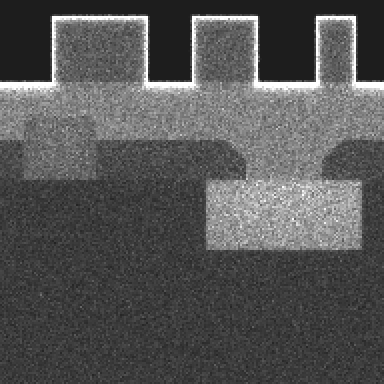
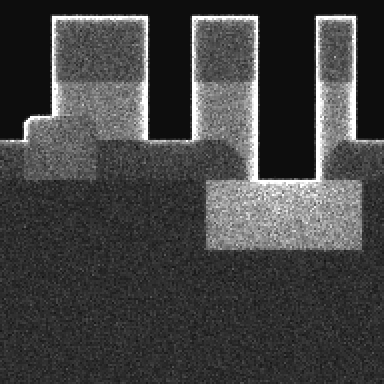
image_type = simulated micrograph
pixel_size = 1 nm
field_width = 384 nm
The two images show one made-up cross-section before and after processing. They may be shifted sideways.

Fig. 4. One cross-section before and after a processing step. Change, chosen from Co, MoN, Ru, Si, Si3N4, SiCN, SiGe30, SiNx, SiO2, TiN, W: SiO2 removed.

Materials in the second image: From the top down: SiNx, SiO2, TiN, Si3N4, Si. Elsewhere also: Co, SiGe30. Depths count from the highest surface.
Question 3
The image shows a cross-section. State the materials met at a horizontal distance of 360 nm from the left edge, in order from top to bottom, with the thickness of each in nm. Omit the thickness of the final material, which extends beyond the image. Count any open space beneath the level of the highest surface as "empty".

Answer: empty 124, SiGe30 40, Co 70, Si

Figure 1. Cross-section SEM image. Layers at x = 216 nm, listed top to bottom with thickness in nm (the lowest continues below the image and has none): SiNx 66, SiO2 58, SiGe30 40, Co 70, Si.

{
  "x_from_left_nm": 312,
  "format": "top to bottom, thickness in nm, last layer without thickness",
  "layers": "empty 164, Co 70, Si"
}